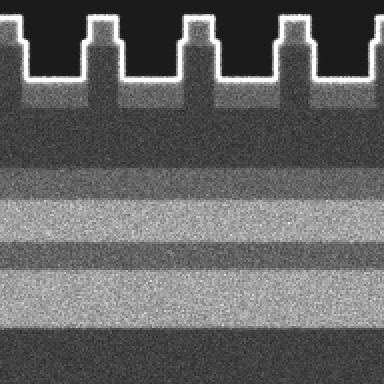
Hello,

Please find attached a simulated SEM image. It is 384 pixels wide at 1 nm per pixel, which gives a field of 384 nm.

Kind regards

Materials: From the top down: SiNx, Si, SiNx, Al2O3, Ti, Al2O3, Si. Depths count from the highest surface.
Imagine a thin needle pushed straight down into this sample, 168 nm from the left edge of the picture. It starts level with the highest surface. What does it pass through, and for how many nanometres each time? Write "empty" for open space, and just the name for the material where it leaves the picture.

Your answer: empty 62, SiNx 30, Si 60, SiNx 32, Al2O3 42, Ti 28, Al2O3 58, Si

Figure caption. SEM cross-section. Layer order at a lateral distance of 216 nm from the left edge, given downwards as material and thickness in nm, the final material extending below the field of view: empty 24, SiNx 68, Si 60, SiNx 32, Al2O3 42, Ti 28, Al2O3 58, Si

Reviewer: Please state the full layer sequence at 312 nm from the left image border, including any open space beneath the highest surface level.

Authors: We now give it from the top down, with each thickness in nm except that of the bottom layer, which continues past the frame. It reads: empty 24, SiNx 68, Si 60, SiNx 32, Al2O3 42, Ti 28, Al2O3 58, Si